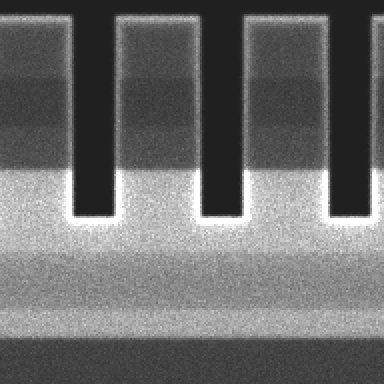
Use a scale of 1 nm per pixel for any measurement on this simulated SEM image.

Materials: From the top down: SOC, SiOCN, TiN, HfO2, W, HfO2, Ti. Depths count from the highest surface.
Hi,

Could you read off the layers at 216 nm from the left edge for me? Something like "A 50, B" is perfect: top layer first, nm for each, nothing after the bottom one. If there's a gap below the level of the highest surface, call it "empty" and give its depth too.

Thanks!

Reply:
empty 202, HfO2 34, W 58, HfO2 28, Ti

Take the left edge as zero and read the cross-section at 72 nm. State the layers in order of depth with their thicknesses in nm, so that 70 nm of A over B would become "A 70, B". empty 202, HfO2 34, W 58, HfO2 28, Ti